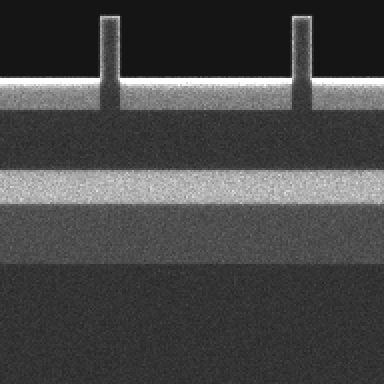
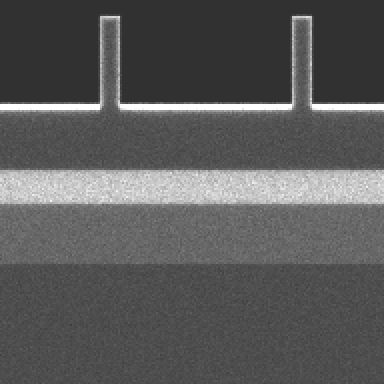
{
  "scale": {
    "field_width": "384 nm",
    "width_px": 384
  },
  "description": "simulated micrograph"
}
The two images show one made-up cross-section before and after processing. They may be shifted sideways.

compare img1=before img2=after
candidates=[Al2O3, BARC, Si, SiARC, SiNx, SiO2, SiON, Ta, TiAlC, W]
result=removed:Al2O3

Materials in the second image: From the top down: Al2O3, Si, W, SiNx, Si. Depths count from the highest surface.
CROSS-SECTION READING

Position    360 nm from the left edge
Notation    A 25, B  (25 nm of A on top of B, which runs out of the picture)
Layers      empty 88, Al2O3 6, Si 60, W 34, SiNx 60, Si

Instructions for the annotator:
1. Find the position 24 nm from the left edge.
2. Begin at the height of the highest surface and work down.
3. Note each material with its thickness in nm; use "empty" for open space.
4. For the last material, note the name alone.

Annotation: empty 88, Al2O3 6, Si 60, W 34, SiNx 60, Si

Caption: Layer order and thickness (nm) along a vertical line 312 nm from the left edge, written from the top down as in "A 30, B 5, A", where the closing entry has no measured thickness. empty 88, Al2O3 6, Si 60, W 34, SiNx 60, Si